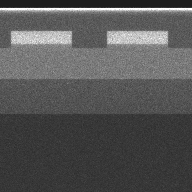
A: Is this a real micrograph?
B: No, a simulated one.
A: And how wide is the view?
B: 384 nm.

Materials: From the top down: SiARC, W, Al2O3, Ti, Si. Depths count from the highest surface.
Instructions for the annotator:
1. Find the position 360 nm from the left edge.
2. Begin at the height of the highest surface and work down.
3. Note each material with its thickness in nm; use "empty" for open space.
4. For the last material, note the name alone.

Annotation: SiARC 80, Al2O3 62, Ti 70, Si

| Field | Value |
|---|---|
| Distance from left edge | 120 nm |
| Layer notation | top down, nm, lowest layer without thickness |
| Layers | SiARC 46, W 26, Al2O3 70, Ti 70, Si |